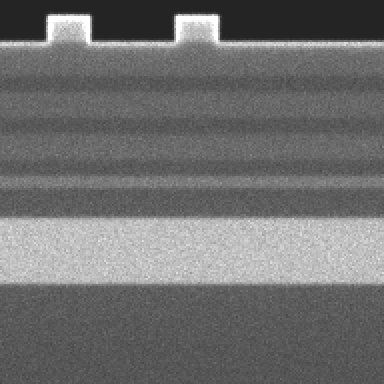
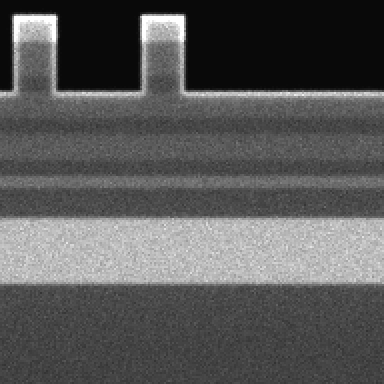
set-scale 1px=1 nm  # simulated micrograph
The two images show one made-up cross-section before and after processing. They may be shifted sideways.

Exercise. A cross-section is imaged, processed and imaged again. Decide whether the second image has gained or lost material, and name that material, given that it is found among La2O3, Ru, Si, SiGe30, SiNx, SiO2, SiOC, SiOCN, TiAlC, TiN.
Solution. removed: Si and SiGe30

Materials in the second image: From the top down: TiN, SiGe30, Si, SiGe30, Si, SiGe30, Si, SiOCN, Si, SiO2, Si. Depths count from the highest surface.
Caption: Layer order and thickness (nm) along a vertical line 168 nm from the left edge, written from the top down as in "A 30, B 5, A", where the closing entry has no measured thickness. TiN 26, SiGe30 34, Si 16, SiGe30 26, Si 16, SiGe30 26, Si 16, SiOCN 12, Si 30, SiO2 66, Si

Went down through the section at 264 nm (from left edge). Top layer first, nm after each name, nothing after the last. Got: empty 76, SiGe30 26, Si 16, SiGe30 26, Si 16, SiOCN 12, Si 30, SiO2 66, Si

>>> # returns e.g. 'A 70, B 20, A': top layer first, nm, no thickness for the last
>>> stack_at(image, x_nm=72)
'empty 76, SiGe30 26, Si 16, SiGe30 26, Si 16, SiOCN 12, Si 30, SiO2 66, Si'